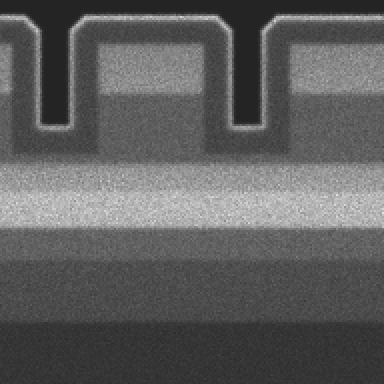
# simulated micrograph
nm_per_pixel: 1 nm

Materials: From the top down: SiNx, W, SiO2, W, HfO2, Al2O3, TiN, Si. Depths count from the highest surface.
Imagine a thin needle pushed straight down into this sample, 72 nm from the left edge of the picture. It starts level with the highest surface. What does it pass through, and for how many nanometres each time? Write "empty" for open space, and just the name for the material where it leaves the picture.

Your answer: empty 12, SiNx 126, SiO2 10, W 28, HfO2 36, Al2O3 32, TiN 62, Si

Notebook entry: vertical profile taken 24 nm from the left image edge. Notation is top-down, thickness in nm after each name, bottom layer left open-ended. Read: SiNx 138, SiO2 10, W 28, HfO2 36, Al2O3 32, TiN 62, Si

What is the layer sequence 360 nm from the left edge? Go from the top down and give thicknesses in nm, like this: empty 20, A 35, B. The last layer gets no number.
SiNx 28, W 50, SiO2 70, W 28, HfO2 36, Al2O3 32, TiN 62, Si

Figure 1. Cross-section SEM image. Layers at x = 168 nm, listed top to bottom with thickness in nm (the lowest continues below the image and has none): SiNx 28, W 50, SiO2 70, W 28, HfO2 36, Al2O3 32, TiN 62, Si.